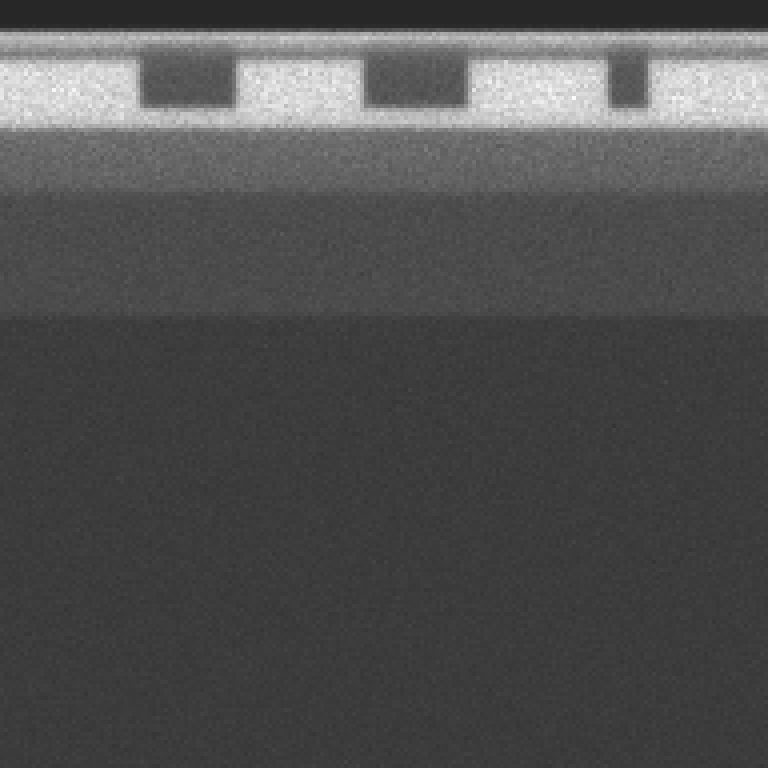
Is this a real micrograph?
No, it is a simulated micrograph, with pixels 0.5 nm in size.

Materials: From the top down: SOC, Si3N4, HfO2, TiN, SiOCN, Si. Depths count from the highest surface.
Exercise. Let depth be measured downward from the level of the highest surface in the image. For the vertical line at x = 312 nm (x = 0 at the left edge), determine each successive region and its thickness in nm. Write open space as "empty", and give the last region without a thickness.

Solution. SOC 38, HfO2 10, TiN 32, SiOCN 62, Si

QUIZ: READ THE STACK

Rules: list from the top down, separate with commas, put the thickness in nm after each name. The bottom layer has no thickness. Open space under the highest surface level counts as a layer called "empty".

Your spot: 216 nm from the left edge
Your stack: SOC 38, HfO2 10, TiN 32, SiOCN 62, Si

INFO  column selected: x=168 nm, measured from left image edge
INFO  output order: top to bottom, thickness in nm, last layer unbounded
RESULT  SOC 6, Si3N4 8, HfO2 34, TiN 32, SiOCN 62, Si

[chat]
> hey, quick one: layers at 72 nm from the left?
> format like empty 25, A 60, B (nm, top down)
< SOC 38, HfO2 10, TiN 32, SiOCN 62, Si